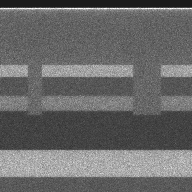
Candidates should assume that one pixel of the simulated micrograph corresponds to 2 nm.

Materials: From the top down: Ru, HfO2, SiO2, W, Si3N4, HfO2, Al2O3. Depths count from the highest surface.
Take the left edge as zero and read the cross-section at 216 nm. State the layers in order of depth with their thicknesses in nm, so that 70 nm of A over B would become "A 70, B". Ru 114, HfO2 24, SiO2 38, W 30, Si3N4 78, HfO2 54, Al2O3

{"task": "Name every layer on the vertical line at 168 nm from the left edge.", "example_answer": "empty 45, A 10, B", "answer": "Ru 114, HfO2 24, SiO2 38, W 30, Si3N4 78, HfO2 54, Al2O3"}